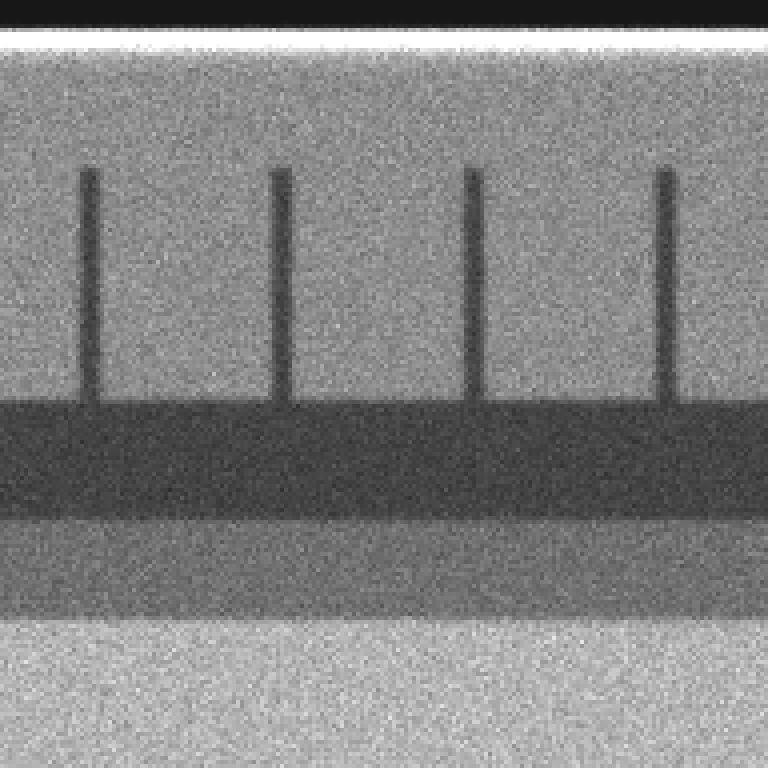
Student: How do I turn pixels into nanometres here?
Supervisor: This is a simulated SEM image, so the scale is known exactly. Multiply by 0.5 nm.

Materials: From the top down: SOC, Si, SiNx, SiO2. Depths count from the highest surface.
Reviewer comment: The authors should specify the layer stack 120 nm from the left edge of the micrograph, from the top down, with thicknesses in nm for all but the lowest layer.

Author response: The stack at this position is SOC 184, Si 60, SiNx 50, SiO2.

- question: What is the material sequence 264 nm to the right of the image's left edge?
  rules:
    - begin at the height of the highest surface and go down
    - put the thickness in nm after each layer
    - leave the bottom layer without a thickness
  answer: SOC 184, Si 60, SiNx 50, SiO2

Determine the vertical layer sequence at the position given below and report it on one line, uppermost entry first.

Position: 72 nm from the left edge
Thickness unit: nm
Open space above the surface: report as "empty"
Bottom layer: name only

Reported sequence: SOC 184, Si 60, SiNx 50, SiO2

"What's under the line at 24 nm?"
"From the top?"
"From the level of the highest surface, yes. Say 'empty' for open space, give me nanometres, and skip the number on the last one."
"SOC 184, Si 60, SiNx 50, SiO2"